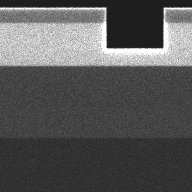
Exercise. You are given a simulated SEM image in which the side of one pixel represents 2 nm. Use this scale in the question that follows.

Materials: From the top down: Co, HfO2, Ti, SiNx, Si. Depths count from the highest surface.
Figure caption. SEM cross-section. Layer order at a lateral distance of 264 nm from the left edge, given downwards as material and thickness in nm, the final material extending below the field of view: empty 82, HfO2 34, Ti 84, SiNx 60, Si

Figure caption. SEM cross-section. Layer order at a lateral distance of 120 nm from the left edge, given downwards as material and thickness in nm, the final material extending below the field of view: Co 30, HfO2 86, Ti 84, SiNx 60, Si